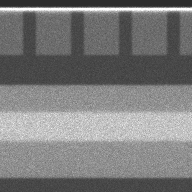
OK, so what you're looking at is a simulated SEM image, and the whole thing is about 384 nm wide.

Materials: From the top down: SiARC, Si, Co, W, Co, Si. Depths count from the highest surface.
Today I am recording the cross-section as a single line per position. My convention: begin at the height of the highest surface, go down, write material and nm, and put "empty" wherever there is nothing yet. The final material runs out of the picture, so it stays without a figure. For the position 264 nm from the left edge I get SiARC 94, Si 60, Co 54, W 58, Co 74, Si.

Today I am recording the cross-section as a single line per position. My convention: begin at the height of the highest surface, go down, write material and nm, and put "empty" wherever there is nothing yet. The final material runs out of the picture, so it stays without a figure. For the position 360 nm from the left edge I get SiARC 94, Si 60, Co 54, W 58, Co 74, Si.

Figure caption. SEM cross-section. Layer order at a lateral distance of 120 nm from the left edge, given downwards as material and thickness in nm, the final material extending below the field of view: SiARC 94, Si 60, Co 54, W 58, Co 74, Si